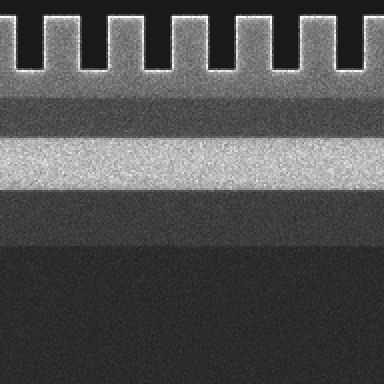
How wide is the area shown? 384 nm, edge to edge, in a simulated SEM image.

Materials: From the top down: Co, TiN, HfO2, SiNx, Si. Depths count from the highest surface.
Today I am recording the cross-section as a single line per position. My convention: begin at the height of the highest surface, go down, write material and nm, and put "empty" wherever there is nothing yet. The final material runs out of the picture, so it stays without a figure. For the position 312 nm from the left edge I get Co 82, TiN 40, HfO2 52, SiNx 56, Si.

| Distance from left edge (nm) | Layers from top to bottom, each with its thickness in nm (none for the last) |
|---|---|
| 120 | Co 82, TiN 40, HfO2 52, SiNx 56, Si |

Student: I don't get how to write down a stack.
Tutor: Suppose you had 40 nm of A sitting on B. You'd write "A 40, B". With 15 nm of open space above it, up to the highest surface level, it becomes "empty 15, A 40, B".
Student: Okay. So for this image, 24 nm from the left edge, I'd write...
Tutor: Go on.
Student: empty 54, Co 28, TiN 40, HfO2 52, SiNx 56, Si